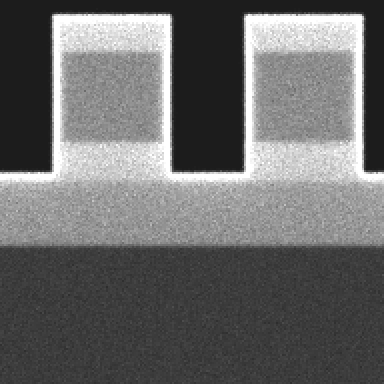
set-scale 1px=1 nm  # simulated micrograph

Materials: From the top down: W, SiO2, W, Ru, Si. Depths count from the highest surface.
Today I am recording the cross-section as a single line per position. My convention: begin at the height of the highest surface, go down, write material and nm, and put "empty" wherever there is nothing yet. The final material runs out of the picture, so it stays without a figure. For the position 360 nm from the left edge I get W 36, SiO2 90, W 40, Ru 64, Si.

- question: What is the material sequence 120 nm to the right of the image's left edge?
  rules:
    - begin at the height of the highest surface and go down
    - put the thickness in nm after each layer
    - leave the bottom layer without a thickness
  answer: W 36, SiO2 90, W 40, Ru 64, Si